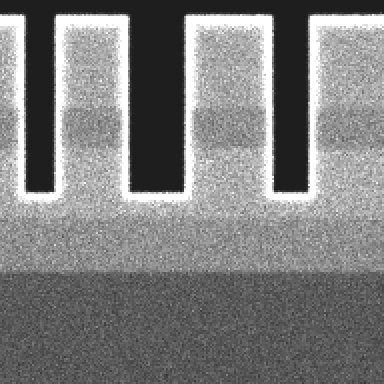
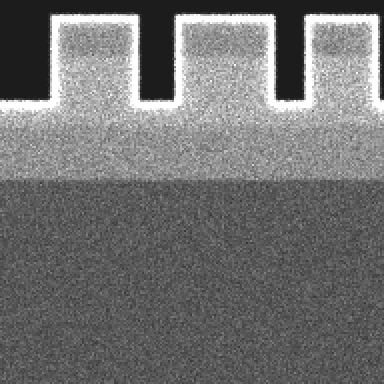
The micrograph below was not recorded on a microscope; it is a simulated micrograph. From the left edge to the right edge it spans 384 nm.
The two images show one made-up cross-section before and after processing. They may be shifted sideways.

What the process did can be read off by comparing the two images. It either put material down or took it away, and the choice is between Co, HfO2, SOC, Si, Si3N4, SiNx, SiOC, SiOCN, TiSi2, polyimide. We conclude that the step removed SOC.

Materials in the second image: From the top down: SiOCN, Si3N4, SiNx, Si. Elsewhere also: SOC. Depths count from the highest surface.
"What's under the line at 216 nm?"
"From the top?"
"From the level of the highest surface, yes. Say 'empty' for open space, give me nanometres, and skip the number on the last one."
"SiOCN 40, Si3N4 70, SiNx 54, Si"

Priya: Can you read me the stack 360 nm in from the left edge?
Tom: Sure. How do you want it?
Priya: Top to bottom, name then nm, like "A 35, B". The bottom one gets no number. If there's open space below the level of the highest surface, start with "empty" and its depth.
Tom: SiOCN 40, Si3N4 70, SiNx 54, Si